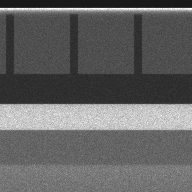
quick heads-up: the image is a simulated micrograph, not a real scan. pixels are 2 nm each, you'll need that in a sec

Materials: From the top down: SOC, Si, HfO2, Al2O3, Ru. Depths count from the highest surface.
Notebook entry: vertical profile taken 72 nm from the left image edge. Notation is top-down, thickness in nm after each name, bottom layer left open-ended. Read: SOC 132, Si 60, HfO2 52, Al2O3 70, Ru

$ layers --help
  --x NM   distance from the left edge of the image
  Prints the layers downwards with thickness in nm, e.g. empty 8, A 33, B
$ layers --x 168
SOC 132, Si 60, HfO2 52, Al2O3 70, Ru